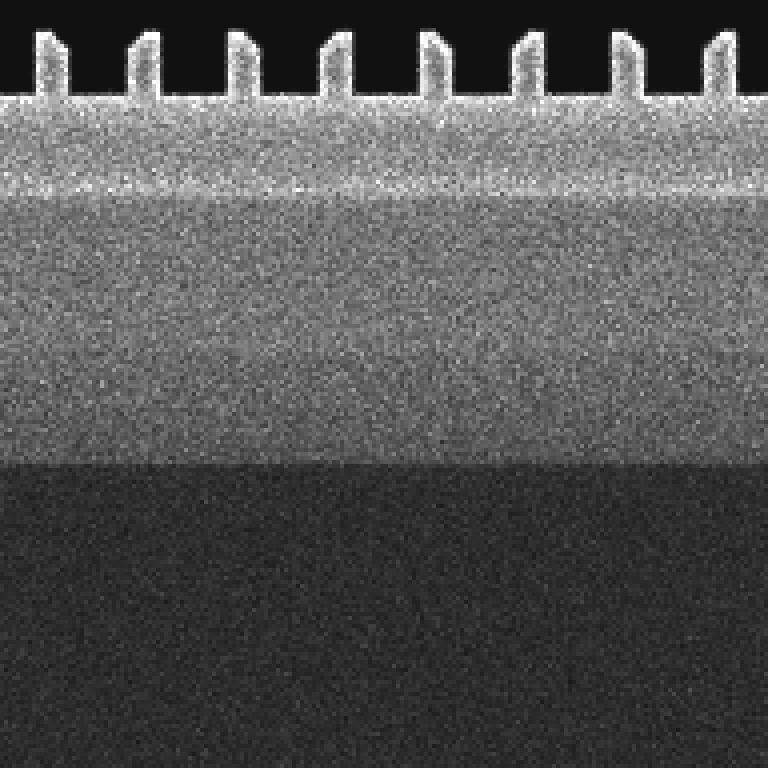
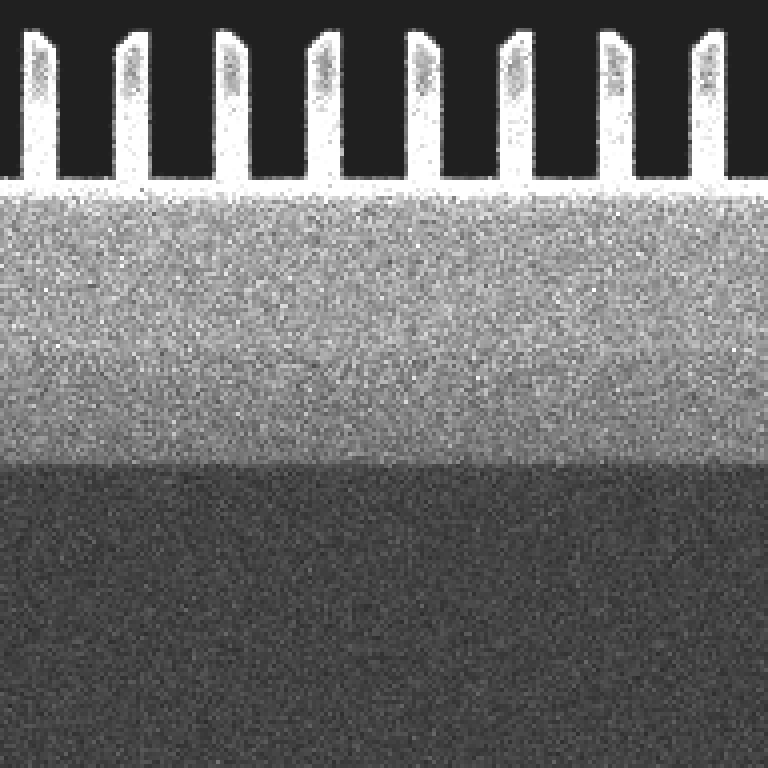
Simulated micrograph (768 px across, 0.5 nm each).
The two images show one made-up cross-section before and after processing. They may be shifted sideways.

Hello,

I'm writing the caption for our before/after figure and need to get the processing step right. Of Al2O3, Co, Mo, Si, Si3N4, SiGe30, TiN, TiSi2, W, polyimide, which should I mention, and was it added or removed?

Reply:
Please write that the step removed W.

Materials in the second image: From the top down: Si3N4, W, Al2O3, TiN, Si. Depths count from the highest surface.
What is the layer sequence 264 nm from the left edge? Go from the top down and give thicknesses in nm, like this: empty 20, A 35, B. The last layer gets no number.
Si3N4 32, W 50, Al2O3 78, TiN 56, Si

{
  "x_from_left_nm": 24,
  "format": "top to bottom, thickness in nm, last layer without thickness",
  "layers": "empty 6, Si3N4 26, W 50, Al2O3 78, TiN 56, Si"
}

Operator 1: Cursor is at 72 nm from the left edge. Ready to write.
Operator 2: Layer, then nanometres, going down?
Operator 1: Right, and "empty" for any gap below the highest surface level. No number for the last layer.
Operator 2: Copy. Si3N4 32, W 50, Al2O3 78, TiN 56, Si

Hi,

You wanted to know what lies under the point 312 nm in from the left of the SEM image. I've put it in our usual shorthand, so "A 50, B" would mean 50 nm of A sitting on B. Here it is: empty 6, Si3N4 26, W 50, Al2O3 78, TiN 56, Si